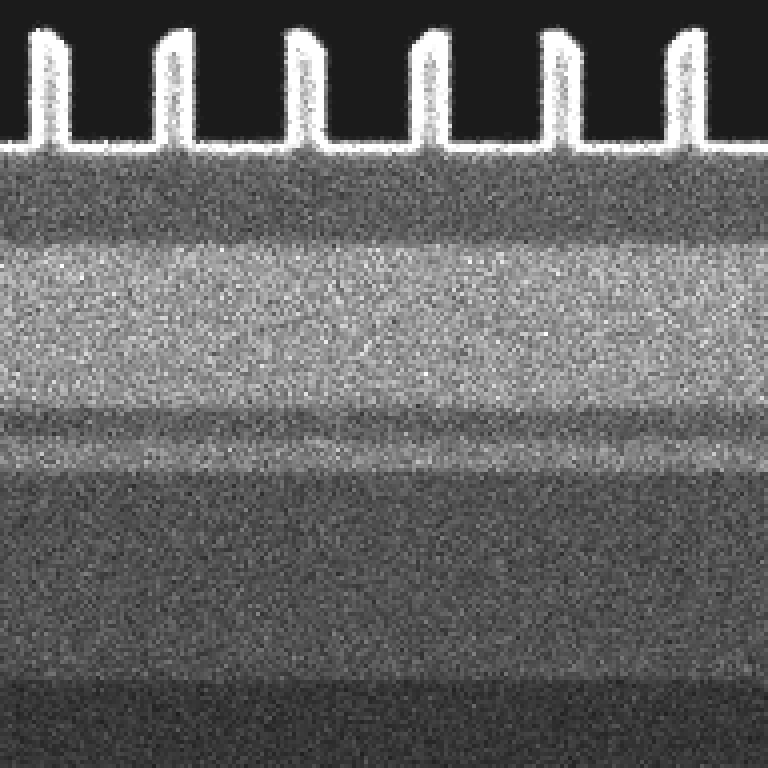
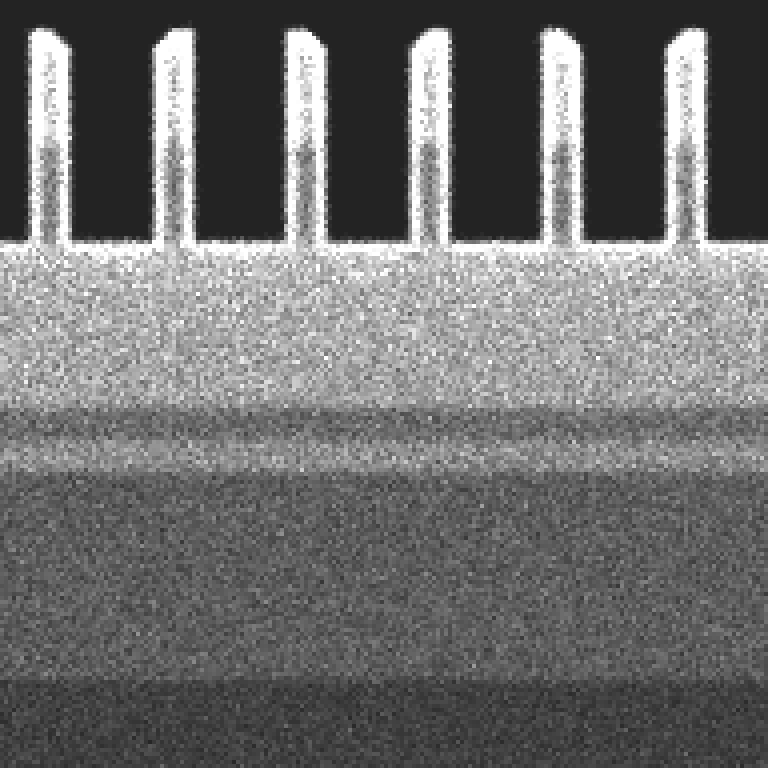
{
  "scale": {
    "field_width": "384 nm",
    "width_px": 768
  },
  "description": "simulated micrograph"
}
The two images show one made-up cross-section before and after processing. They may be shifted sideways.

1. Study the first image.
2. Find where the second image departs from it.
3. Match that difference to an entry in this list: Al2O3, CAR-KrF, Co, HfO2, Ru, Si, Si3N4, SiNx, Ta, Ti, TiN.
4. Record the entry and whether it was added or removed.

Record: Si3N4 / removed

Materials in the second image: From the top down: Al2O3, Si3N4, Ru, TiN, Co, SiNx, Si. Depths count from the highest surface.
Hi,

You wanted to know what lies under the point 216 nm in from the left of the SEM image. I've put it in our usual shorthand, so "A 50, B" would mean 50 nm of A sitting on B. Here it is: Al2O3 56, Si3N4 50, Ru 82, TiN 16, Co 16, SiNx 104, Si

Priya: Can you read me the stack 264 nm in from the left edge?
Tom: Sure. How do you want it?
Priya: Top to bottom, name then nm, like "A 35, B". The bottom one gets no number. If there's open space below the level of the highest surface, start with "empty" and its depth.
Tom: empty 106, Ru 82, TiN 16, Co 16, SiNx 104, Si